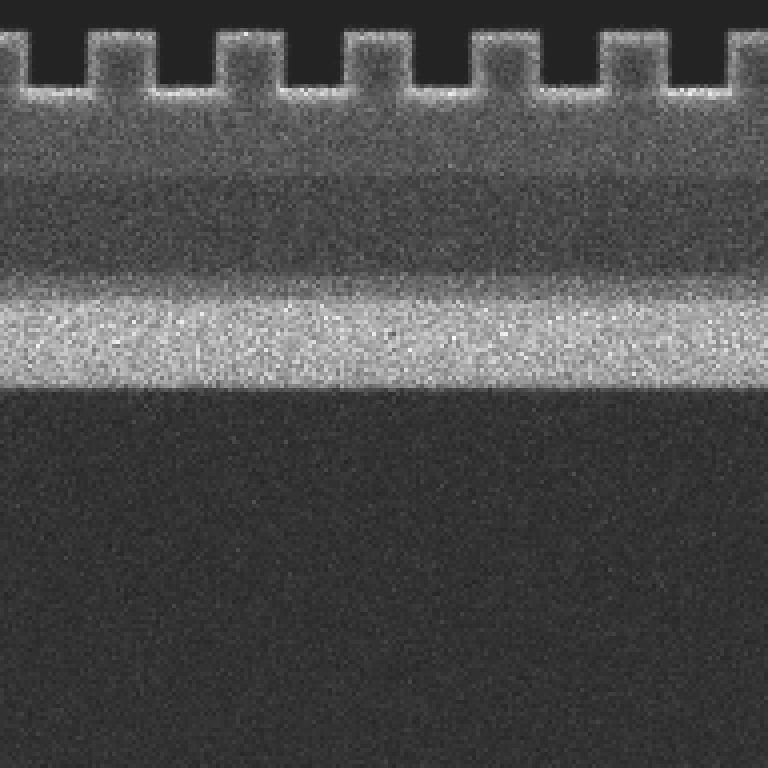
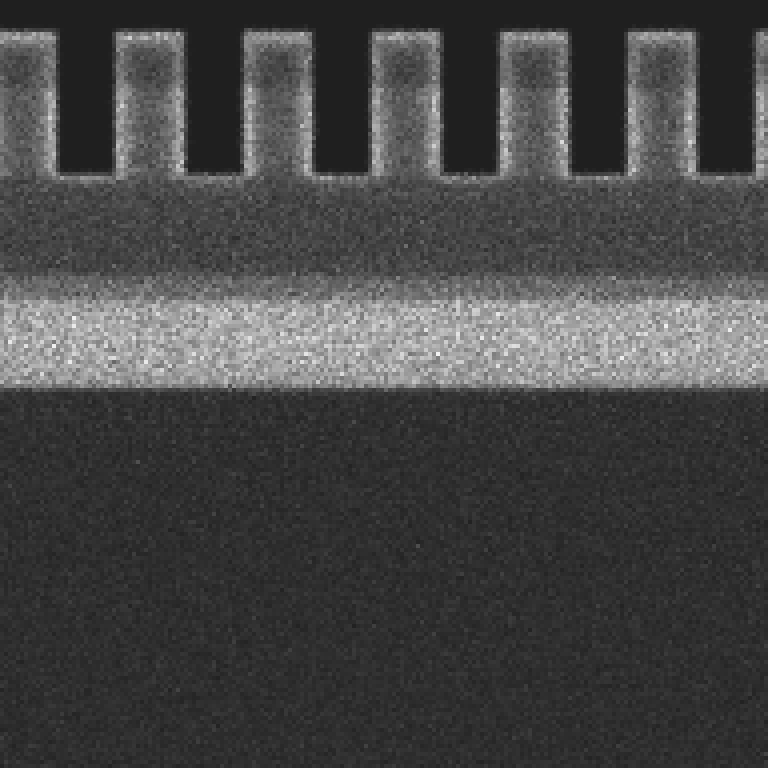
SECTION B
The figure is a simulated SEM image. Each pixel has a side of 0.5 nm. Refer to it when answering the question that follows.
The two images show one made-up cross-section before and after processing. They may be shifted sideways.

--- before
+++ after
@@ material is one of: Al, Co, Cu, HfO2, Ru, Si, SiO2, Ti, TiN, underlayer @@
SiO2 removed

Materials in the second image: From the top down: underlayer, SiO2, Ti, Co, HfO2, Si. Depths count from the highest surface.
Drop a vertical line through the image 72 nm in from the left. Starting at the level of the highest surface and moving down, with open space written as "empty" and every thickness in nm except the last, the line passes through underlayer 28, SiO2 44, Ti 50, Co 12, HfO2 44, Si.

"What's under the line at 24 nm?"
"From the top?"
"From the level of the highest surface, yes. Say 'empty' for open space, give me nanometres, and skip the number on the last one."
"underlayer 28, SiO2 44, Ti 50, Co 12, HfO2 44, Si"